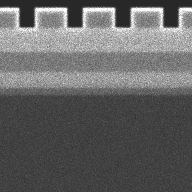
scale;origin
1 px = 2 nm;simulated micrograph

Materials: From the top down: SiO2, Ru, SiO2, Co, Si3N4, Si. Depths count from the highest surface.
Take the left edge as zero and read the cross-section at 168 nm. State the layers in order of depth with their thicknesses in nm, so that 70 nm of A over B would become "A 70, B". SiO2 40, Ru 48, SiO2 40, Co 32, Si3N4 14, Si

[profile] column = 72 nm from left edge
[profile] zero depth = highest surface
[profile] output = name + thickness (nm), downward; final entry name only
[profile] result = SiO2 40, Ru 48, SiO2 40, Co 32, Si3N4 14, Si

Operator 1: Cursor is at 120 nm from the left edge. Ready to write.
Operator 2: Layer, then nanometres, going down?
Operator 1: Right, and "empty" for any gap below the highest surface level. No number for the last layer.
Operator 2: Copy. SiO2 40, Ru 48, SiO2 40, Co 32, Si3N4 14, Si